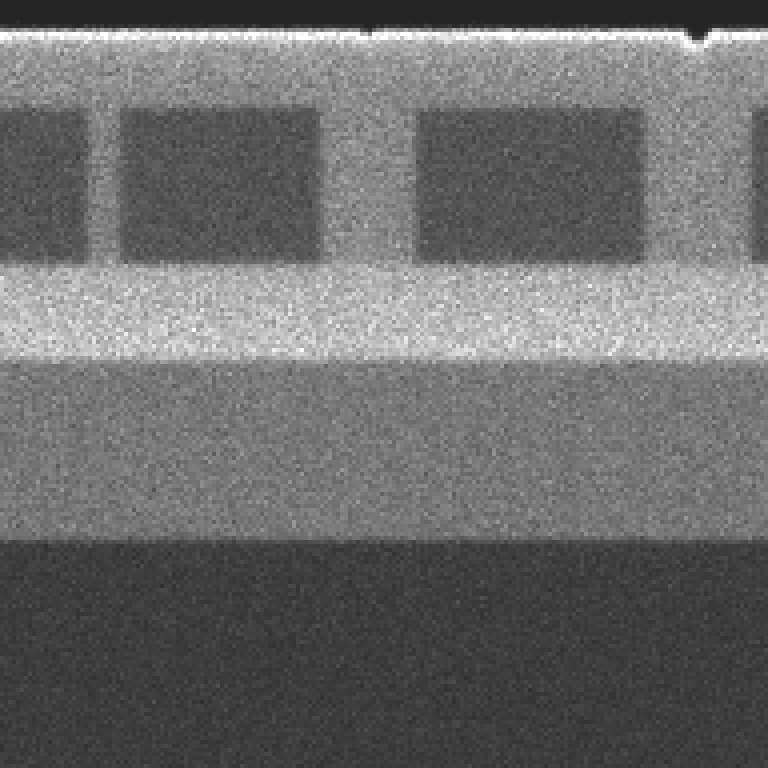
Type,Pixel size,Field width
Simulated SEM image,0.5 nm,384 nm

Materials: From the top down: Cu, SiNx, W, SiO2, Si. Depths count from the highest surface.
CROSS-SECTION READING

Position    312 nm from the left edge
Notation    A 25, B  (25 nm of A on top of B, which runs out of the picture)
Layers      Cu 38, SiNx 78, W 48, SiO2 90, Si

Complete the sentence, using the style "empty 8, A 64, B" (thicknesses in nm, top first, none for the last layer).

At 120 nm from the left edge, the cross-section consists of Cu 38, SiNx 78, W 48, SiO2 90, Si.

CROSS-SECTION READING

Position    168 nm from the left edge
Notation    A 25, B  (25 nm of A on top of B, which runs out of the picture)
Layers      Cu 116, W 48, SiO2 90, Si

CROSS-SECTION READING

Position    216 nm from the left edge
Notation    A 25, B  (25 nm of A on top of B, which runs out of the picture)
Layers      Cu 38, SiNx 78, W 48, SiO2 90, Si